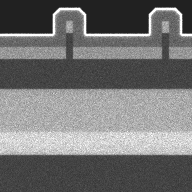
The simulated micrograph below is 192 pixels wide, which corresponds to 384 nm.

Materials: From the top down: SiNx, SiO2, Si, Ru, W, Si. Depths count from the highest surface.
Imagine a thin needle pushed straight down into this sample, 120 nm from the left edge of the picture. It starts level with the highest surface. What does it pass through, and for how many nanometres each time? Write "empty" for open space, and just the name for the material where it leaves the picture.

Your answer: SiNx 78, SiO2 24, Si 60, Ru 86, W 46, Si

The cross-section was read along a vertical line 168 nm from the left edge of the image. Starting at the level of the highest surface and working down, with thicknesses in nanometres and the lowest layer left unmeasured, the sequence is empty 10, SiNx 68, SiO2 24, Si 60, Ru 86, W 46, Si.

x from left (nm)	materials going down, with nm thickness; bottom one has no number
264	empty 52, SiNx 26, SiO2 24, Si 60, Ru 86, W 46, Si